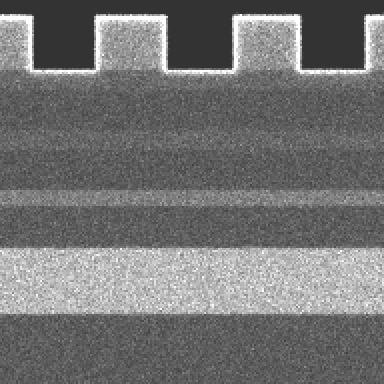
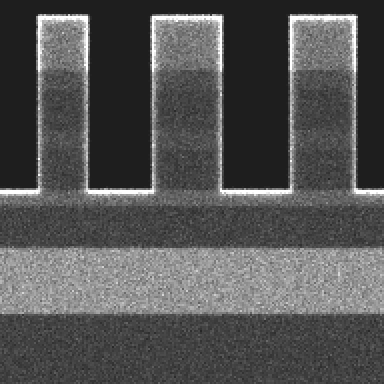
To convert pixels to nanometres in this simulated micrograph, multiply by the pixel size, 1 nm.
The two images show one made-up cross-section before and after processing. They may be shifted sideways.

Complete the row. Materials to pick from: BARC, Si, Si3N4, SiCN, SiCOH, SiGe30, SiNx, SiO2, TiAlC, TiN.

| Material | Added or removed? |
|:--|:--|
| Si and SiGe30 | removed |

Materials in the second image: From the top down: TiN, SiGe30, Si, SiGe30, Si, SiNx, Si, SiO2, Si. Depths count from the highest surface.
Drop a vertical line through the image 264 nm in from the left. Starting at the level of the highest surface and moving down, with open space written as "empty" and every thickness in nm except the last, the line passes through empty 174, SiNx 16, Si 42, SiO2 66, Si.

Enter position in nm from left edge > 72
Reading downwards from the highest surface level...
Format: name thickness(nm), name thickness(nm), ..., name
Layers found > TiN 54, SiGe30 20, Si 40, SiGe30 20, Si 40, SiNx 16, Si 42, SiO2 66, Si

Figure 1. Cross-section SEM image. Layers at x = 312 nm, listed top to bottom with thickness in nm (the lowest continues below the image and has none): TiN 54, SiGe30 20, Si 40, SiGe30 20, Si 40, SiNx 16, Si 42, SiO2 66, Si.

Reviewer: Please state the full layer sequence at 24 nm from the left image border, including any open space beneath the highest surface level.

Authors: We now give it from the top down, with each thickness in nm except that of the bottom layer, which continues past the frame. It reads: empty 174, SiNx 16, Si 42, SiO2 66, Si